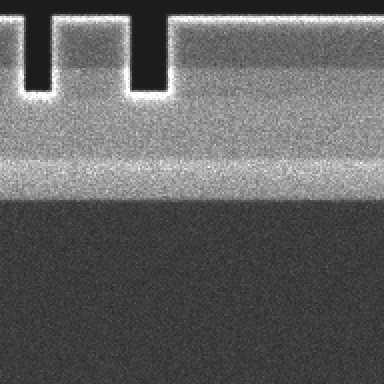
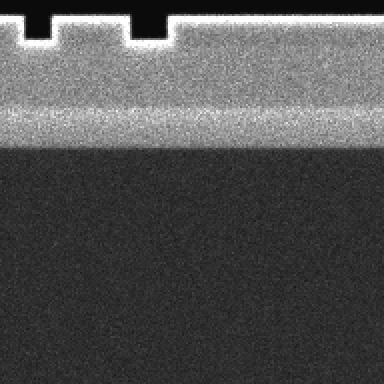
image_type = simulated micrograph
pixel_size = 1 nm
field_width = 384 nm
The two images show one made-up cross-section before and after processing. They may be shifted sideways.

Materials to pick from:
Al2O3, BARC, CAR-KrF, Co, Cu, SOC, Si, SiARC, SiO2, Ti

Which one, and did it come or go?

SOC - removed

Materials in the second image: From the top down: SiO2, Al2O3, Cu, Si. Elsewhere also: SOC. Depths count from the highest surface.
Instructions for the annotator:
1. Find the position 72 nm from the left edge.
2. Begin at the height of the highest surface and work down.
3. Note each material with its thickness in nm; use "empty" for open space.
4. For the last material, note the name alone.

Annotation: SiO2 30, Al2O3 62, Cu 40, Si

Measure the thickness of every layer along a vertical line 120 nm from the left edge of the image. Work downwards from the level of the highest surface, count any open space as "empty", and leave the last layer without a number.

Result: SiO2 30, Al2O3 62, Cu 40, Si